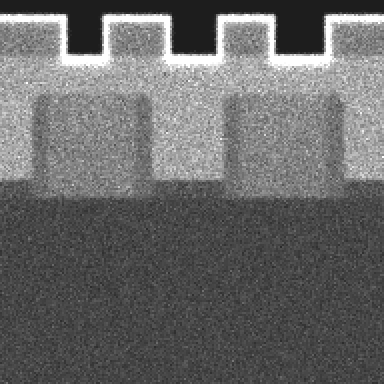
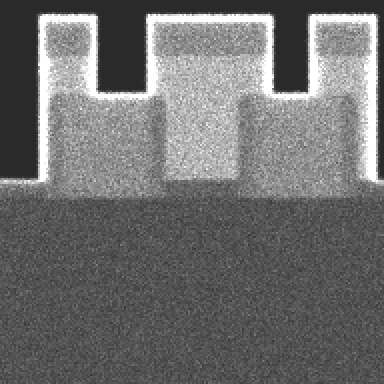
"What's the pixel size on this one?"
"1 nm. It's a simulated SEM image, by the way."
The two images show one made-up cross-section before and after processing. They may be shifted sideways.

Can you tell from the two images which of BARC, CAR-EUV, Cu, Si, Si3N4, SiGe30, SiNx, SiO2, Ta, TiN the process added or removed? Yes, it removed SiO2.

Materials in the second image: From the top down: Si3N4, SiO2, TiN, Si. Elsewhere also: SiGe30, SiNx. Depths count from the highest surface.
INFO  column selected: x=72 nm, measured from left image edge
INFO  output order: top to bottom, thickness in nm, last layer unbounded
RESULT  Si3N4 40, SiO2 38, TiN 104, Si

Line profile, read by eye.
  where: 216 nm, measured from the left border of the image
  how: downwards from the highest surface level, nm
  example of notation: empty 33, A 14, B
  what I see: Si3N4 40, SiO2 124, SiGe30 18, Si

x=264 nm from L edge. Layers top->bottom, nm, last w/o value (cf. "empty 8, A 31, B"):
Si3N4 40, SiO2 38, TiN 104, Si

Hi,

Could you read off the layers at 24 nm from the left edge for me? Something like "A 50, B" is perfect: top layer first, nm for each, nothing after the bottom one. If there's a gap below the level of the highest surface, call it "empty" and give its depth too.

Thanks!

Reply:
empty 164, SiGe30 18, Si